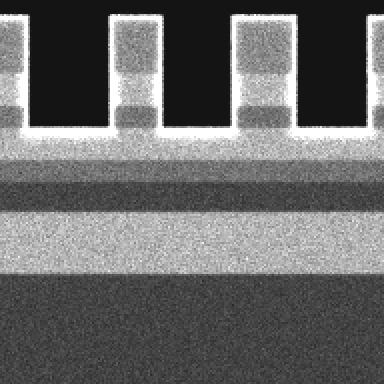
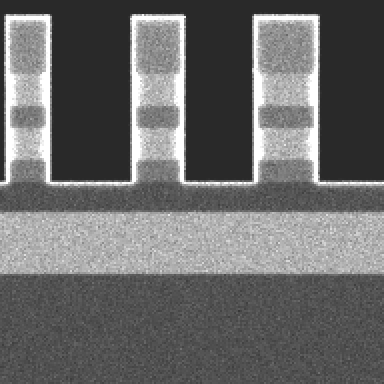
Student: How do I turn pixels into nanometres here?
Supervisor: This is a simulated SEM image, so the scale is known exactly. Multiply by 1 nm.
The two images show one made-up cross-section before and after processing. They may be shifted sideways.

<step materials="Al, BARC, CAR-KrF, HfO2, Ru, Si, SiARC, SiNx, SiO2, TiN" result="removed SiNx and SiO2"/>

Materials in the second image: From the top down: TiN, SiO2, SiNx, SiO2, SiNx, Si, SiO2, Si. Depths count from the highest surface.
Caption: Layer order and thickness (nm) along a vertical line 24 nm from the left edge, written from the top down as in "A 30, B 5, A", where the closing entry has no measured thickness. TiN 58, SiO2 32, SiNx 22, SiO2 32, SiNx 22, Si 30, SiO2 62, Si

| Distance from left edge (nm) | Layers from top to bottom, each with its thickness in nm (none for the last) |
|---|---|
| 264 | TiN 58, SiO2 32, SiNx 22, SiO2 32, SiNx 22, Si 30, SiO2 62, Si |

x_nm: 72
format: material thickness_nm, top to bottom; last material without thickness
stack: empty 166, Si 30, SiO2 62, Si